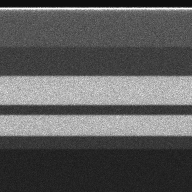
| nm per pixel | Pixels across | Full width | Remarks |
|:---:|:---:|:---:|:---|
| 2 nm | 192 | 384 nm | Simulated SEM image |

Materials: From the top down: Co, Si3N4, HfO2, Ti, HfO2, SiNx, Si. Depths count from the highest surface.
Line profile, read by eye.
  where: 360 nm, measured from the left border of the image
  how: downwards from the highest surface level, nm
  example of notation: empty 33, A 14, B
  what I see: Co 78, Si3N4 58, HfO2 58, Ti 20, HfO2 42, SiNx 26, Si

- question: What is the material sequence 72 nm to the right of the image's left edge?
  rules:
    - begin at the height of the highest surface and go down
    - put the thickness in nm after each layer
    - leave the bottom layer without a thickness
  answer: Co 78, Si3N4 58, HfO2 58, Ti 20, HfO2 42, SiNx 26, Si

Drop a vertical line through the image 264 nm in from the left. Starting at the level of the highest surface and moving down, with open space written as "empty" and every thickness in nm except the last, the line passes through Co 78, Si3N4 58, HfO2 58, Ti 20, HfO2 42, SiNx 26, Si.